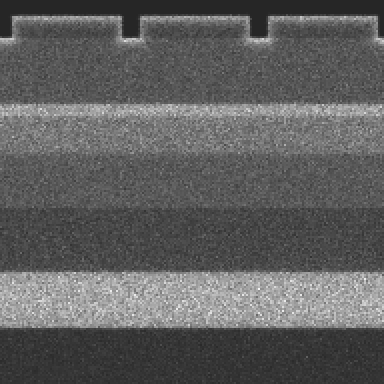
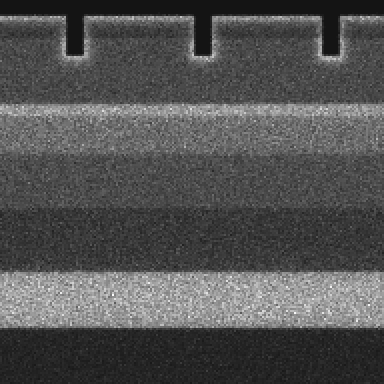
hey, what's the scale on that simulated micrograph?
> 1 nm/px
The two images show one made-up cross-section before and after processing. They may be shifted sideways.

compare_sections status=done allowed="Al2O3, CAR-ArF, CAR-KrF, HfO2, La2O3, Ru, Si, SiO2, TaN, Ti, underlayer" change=removed material="SiO2"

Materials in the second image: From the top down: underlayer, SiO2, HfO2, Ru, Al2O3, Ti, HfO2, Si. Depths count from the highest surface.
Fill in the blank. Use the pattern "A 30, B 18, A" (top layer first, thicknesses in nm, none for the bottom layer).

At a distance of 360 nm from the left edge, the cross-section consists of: underlayer 22, SiO2 66, HfO2 12, Ru 38, Al2O3 54, Ti 64, HfO2 56, Si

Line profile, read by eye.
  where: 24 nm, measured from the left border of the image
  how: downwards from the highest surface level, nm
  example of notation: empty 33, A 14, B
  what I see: underlayer 22, SiO2 66, HfO2 12, Ru 38, Al2O3 54, Ti 64, HfO2 56, Si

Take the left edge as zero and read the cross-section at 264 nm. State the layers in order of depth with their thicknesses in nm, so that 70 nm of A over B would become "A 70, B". underlayer 22, SiO2 66, HfO2 12, Ru 38, Al2O3 54, Ti 64, HfO2 56, Si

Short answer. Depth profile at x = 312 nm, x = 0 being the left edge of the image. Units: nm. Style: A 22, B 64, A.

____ underlayer 22, SiO2 66, HfO2 12, Ru 38, Al2O3 54, Ti 64, HfO2 56, Si